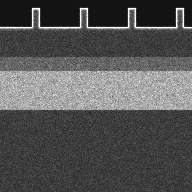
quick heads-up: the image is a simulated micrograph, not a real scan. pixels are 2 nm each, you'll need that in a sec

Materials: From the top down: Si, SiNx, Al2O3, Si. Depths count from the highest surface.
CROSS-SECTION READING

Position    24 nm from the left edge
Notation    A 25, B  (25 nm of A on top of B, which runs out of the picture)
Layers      empty 38, Si 60, SiNx 28, Al2O3 78, Si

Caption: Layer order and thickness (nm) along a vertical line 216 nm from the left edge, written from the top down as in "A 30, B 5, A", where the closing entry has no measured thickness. empty 38, Si 60, SiNx 28, Al2O3 78, Si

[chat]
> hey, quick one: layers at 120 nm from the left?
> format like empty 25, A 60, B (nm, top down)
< empty 38, Si 60, SiNx 28, Al2O3 78, Si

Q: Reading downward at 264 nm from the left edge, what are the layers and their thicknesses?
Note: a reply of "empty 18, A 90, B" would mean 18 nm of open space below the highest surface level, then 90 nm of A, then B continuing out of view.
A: Si 98, SiNx 28, Al2O3 78, Si